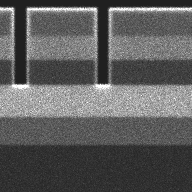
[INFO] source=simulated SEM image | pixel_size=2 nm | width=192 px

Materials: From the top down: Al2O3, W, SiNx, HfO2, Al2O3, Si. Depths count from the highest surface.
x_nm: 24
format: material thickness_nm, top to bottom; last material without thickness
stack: Al2O3 56, W 48, SiNx 50, HfO2 64, Al2O3 56, Si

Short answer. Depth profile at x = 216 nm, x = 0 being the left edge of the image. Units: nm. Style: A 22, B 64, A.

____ empty 154, HfO2 64, Al2O3 56, Si